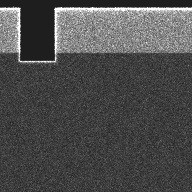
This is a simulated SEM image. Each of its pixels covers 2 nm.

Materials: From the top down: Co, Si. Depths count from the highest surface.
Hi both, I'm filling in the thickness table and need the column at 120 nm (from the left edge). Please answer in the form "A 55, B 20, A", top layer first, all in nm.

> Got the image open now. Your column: Co 90, Si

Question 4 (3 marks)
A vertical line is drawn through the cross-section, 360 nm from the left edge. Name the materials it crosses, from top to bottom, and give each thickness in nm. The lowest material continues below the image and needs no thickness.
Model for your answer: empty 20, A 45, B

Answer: Co 90, Si